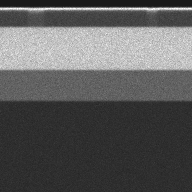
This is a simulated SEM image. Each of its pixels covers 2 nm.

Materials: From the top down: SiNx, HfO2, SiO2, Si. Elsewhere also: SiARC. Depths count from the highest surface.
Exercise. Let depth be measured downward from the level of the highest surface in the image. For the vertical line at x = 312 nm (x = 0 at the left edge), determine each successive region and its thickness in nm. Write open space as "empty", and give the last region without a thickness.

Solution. SiARC 38, HfO2 86, SiO2 62, Si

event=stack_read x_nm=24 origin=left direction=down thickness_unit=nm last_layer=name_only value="SiNx 38, HfO2 86, SiO2 62, Si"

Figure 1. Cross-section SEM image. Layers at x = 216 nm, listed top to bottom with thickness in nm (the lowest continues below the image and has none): SiNx 38, HfO2 86, SiO2 62, Si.